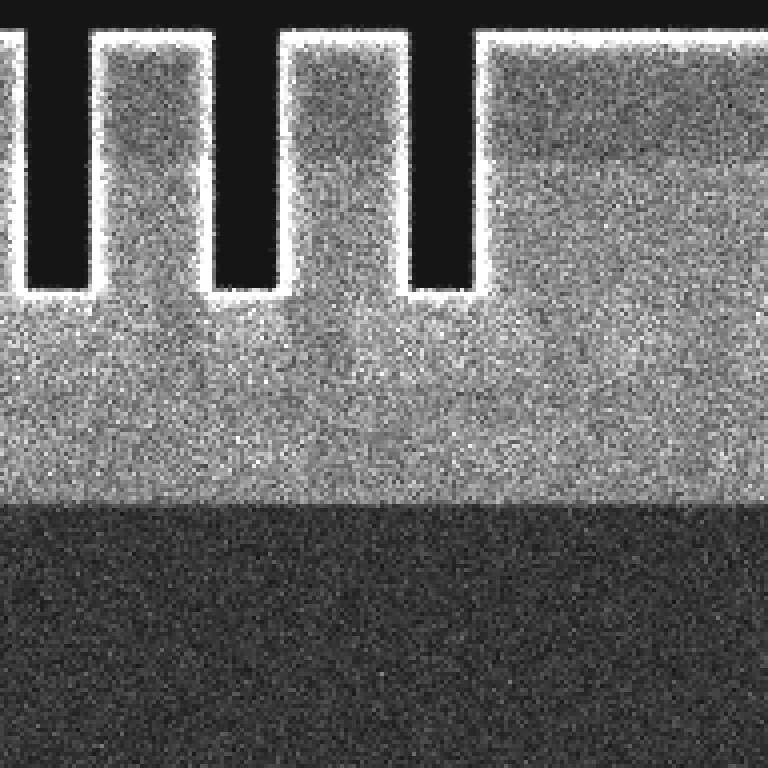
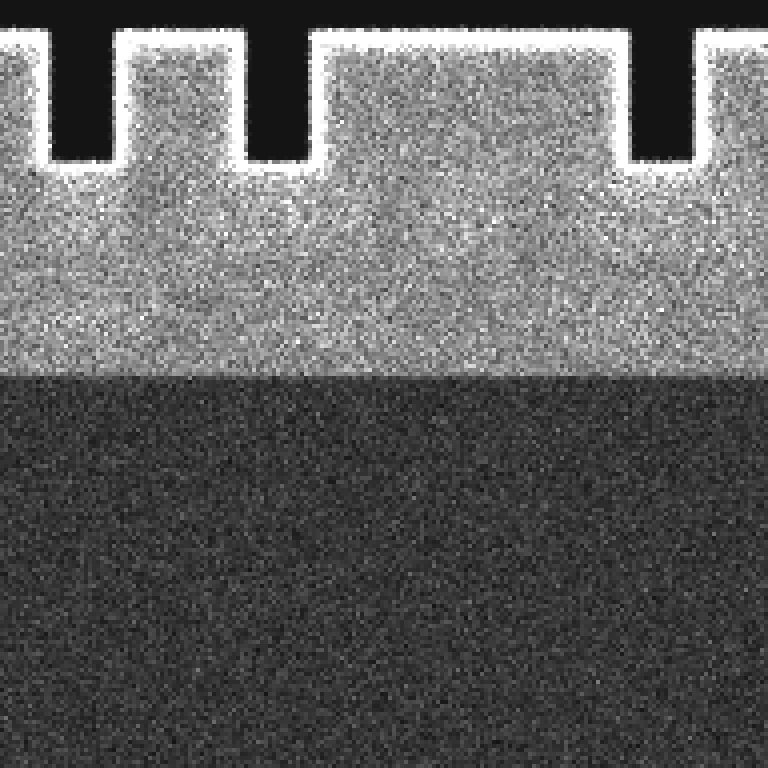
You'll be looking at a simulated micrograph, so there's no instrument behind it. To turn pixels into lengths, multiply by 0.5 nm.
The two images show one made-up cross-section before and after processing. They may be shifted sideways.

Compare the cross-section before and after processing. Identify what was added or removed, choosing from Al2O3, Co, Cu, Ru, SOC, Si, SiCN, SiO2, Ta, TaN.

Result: SOC removed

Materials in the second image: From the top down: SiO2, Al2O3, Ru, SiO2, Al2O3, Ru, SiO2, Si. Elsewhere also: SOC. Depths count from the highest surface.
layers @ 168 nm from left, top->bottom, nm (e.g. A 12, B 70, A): SiO2 52, Al2O3 14, Ru 46, SiO2 14, Al2O3 8, Ru 24, SiO2 14, Si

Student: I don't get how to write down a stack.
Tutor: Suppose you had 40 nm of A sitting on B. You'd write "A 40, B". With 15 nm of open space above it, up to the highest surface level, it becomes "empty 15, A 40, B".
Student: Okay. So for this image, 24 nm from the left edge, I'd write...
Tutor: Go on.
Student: empty 66, Ru 46, SiO2 14, Al2O3 8, Ru 24, SiO2 14, Si